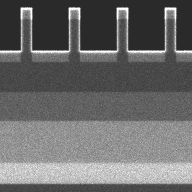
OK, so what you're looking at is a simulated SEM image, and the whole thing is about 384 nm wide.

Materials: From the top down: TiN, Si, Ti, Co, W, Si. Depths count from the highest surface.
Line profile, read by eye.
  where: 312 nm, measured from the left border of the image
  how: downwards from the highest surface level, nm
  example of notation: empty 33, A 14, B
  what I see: empty 86, TiN 22, Si 60, Ti 58, Co 84, W 42, Si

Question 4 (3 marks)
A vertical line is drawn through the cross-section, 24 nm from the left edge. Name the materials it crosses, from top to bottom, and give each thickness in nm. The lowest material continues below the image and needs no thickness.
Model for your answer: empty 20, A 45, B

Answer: empty 86, TiN 22, Si 60, Ti 58, Co 84, W 42, Si